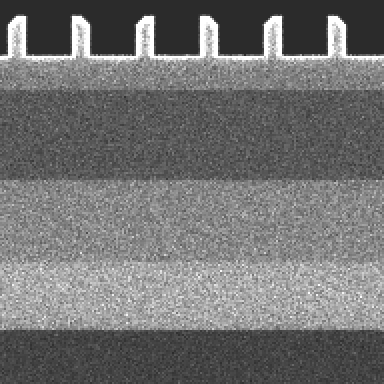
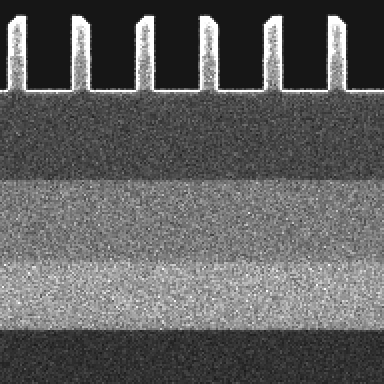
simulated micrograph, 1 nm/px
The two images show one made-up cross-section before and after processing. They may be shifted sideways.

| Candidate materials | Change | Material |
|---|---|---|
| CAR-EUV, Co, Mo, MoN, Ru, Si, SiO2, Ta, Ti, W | removed | Co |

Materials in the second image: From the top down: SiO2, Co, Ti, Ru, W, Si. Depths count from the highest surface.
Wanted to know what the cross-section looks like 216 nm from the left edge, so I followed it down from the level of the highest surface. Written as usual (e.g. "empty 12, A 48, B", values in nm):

empty 8, SiO2 32, Co 34, Ti 90, Ru 82, W 68, Si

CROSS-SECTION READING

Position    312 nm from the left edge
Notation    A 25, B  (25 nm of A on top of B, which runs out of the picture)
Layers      empty 74, Ti 90, Ru 82, W 68, Si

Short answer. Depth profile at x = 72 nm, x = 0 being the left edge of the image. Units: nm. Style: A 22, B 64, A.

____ SiO2 40, Co 34, Ti 90, Ru 82, W 68, Si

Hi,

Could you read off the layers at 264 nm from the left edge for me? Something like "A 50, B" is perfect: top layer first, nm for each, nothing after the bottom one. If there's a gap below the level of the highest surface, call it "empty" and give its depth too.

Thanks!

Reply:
empty 8, SiO2 32, Co 34, Ti 90, Ru 82, W 68, Si